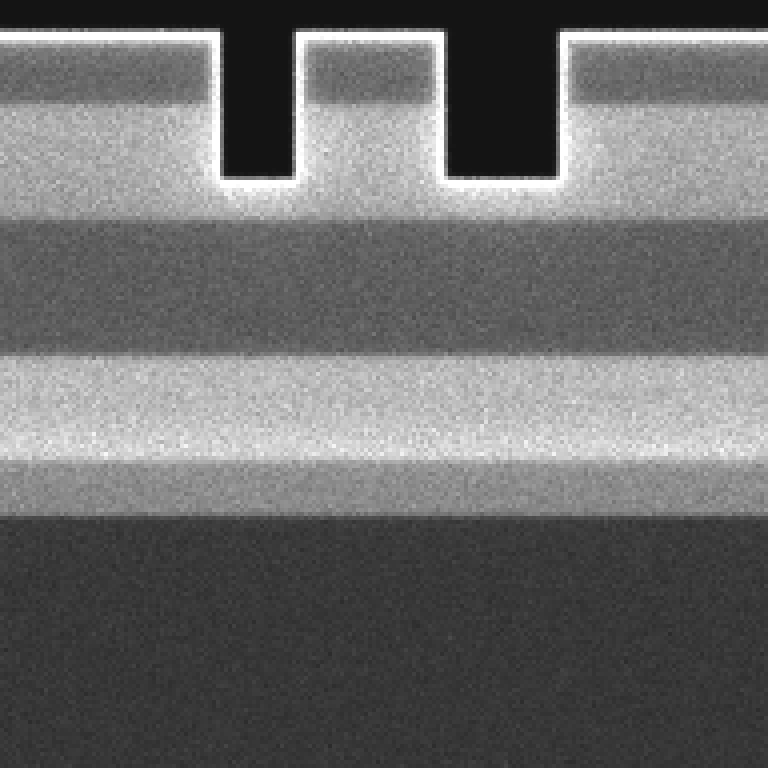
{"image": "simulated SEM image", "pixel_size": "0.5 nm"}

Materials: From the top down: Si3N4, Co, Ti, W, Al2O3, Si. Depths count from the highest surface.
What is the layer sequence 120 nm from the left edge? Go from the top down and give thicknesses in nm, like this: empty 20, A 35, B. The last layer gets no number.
empty 74, Co 20, Ti 68, W 52, Al2O3 28, Si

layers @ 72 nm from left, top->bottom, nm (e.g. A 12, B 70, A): Si3N4 36, Co 58, Ti 68, W 52, Al2O3 28, Si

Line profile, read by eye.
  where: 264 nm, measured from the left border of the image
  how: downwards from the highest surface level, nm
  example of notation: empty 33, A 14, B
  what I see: empty 74, Co 20, Ti 68, W 52, Al2O3 28, Si